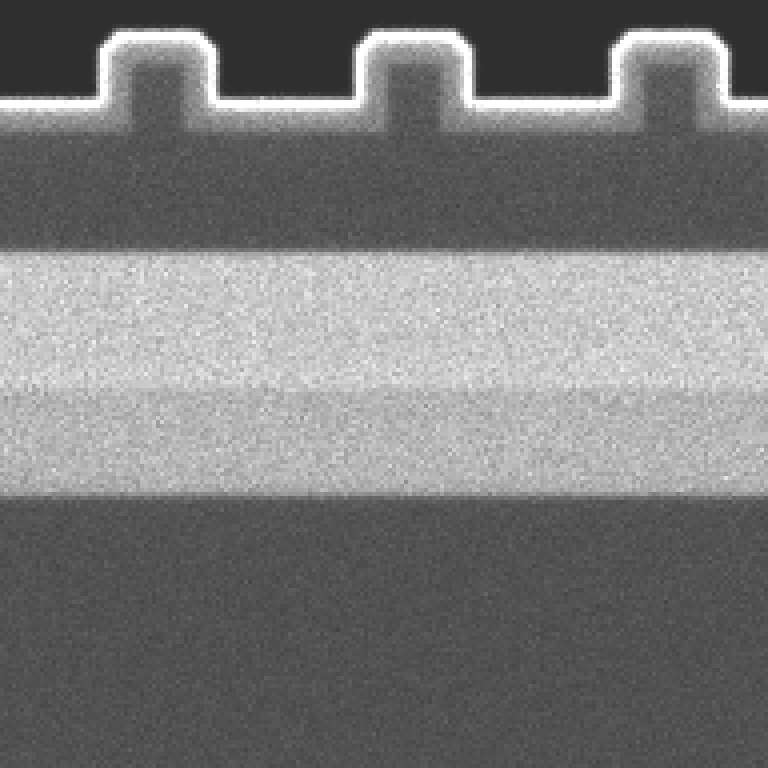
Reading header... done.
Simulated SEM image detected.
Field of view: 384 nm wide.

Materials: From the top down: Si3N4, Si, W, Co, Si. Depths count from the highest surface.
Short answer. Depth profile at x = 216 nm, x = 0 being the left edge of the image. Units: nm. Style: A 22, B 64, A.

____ Si3N4 16, Si 94, W 68, Co 54, Si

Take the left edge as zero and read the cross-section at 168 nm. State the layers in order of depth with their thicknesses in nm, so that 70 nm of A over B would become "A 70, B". empty 34, Si3N4 16, Si 60, W 68, Co 54, Si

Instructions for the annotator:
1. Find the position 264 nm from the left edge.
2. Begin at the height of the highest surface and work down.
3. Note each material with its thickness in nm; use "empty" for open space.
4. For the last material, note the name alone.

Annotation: empty 34, Si3N4 16, Si 60, W 68, Co 54, Si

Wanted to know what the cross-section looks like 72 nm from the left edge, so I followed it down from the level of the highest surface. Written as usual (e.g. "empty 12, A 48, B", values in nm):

Si3N4 16, Si 94, W 68, Co 54, Si